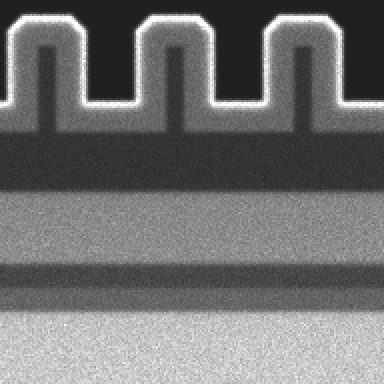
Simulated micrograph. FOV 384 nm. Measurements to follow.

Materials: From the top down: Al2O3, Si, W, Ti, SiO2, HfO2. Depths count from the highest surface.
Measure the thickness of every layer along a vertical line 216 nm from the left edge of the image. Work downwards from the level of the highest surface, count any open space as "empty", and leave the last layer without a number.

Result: empty 86, Al2O3 30, Si 60, W 72, Ti 24, SiO2 24, HfO2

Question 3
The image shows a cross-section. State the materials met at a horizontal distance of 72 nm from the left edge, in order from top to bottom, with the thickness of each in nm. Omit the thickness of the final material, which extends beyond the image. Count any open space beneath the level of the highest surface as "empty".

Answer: empty 2, Al2O3 114, Si 60, W 72, Ti 24, SiO2 24, HfO2